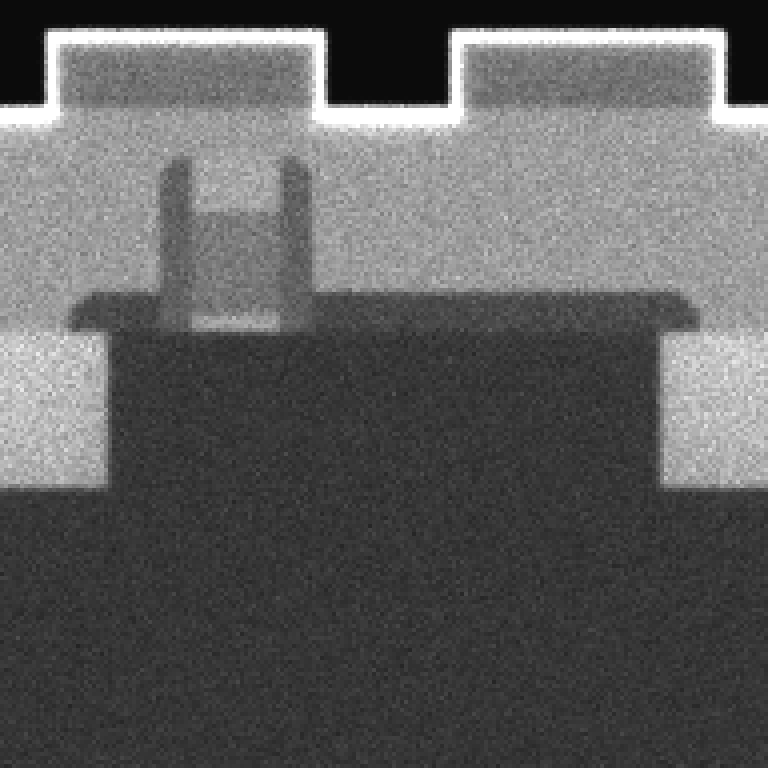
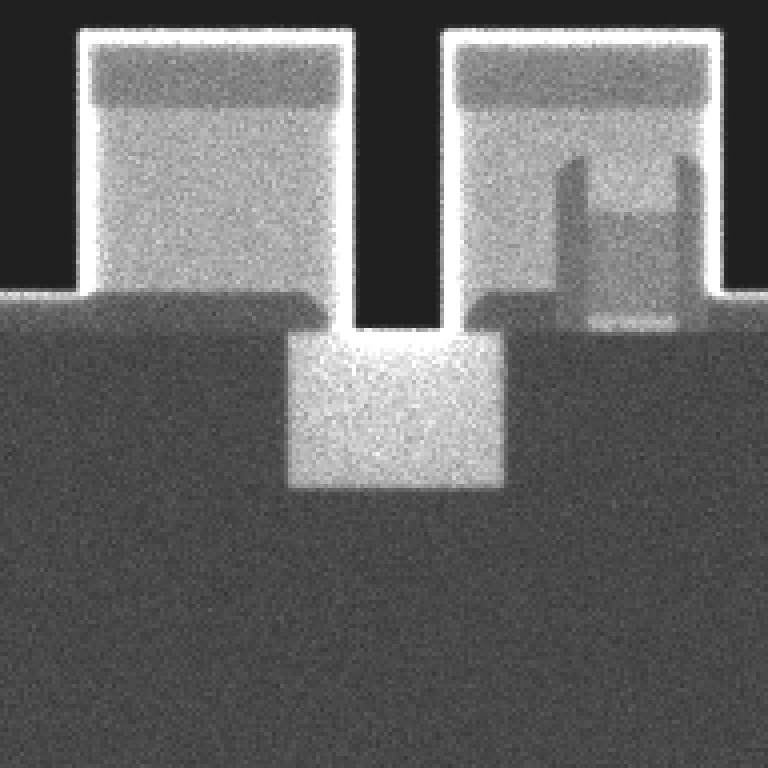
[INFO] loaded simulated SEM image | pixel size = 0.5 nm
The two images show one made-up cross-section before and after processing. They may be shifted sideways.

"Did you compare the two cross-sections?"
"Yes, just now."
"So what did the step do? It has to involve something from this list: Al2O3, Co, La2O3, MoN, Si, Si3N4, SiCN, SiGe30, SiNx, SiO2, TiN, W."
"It removed SiO2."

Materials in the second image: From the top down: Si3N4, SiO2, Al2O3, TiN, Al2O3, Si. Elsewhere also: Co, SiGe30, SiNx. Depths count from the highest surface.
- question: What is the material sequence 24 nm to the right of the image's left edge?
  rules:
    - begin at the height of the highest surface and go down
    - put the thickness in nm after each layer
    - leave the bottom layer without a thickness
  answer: empty 130, SiGe30 20, Si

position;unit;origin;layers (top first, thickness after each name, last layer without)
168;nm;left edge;Si3N4 38, SiO2 112, Co 78, Si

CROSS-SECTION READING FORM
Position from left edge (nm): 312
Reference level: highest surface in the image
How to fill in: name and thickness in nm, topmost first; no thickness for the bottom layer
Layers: Si3N4 38, SiO2 24, Al2O3 28, TiN 52, Al2O3 8, Si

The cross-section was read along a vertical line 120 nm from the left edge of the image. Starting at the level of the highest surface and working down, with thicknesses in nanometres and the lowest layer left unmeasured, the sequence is Si3N4 38, SiO2 92, SiGe30 20, Si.